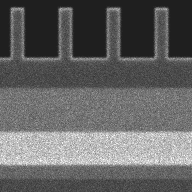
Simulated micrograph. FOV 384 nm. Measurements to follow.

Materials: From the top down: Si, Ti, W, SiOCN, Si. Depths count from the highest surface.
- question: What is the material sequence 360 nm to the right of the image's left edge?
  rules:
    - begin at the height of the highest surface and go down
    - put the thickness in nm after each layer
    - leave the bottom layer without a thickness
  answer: empty 100, Si 60, Ti 88, W 66, SiOCN 28, Si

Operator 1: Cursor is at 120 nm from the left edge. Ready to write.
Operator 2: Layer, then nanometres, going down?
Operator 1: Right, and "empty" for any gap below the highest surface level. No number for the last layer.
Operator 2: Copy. Si 160, Ti 88, W 66, SiOCN 28, Si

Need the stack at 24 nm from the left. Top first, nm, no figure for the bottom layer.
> Si 160, Ti 88, W 66, SiOCN 28, Si